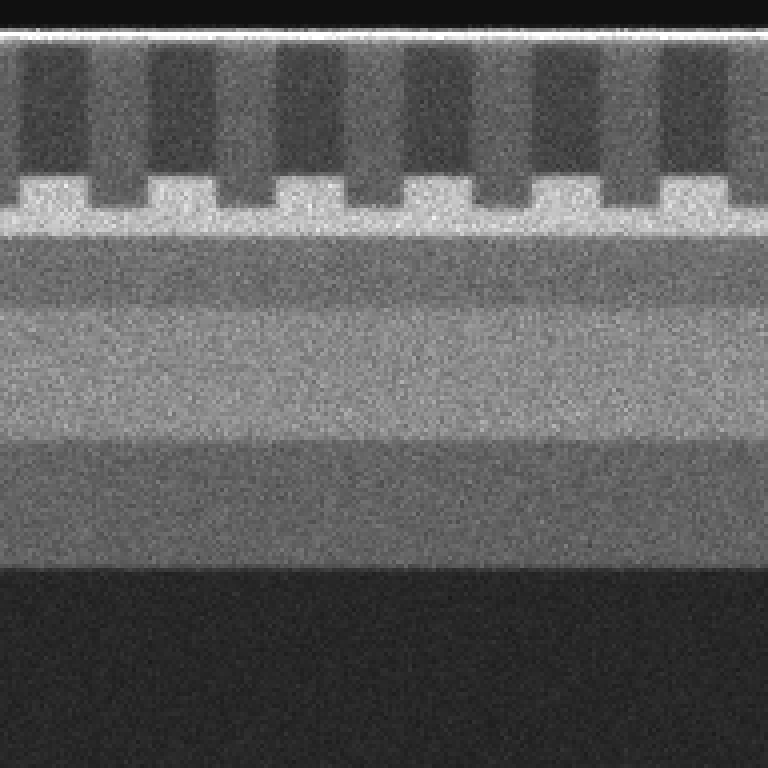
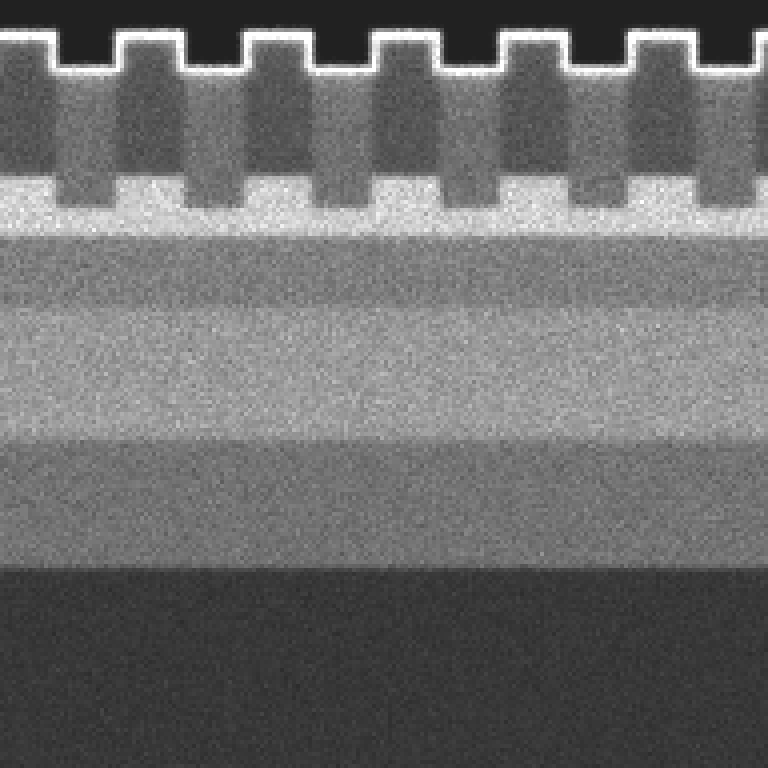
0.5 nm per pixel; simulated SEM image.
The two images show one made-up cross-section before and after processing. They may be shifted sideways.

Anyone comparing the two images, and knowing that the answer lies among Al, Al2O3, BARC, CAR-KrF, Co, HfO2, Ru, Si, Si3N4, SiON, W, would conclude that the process removed Co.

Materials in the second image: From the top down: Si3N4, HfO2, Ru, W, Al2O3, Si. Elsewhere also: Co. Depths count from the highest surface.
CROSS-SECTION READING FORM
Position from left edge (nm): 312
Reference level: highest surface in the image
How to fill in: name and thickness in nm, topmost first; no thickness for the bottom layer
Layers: empty 18, Co 70, HfO2 14, Ru 36, W 66, Al2O3 64, Si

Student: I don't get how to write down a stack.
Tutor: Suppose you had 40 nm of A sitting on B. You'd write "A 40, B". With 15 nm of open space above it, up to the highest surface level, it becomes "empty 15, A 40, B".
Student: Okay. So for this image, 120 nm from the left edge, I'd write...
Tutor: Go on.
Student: empty 18, Co 70, HfO2 14, Ru 36, W 66, Al2O3 64, Si